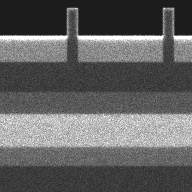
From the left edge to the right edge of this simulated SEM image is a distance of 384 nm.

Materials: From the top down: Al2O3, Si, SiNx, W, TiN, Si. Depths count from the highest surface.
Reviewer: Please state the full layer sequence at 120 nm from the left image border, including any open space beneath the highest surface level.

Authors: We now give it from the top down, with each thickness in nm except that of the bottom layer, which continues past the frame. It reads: empty 56, Al2O3 52, Si 60, SiNx 44, W 66, TiN 38, Si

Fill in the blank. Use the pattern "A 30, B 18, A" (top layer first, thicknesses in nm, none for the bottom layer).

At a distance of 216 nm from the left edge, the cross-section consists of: empty 56, Al2O3 52, Si 60, SiNx 44, W 66, TiN 38, Si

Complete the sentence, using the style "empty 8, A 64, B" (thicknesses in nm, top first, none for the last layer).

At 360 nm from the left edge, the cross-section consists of empty 56, Al2O3 52, Si 60, SiNx 44, W 66, TiN 38, Si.